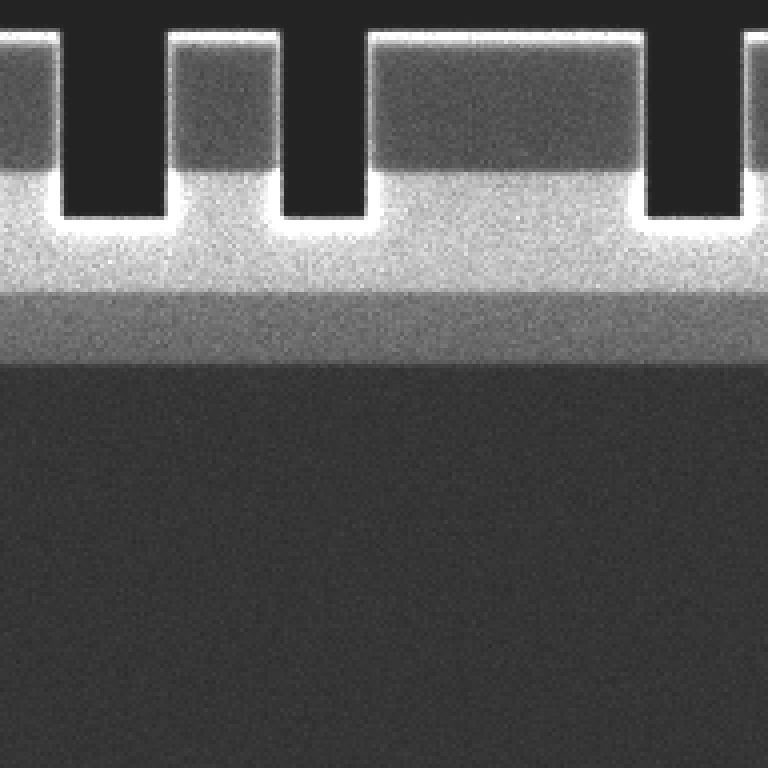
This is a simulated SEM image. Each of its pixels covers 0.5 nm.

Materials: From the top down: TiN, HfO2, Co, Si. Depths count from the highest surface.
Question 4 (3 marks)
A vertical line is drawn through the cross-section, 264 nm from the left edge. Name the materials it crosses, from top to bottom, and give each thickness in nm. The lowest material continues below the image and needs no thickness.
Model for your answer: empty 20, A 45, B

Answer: TiN 70, HfO2 60, Co 36, Si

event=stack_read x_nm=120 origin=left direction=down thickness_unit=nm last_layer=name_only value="TiN 70, HfO2 60, Co 36, Si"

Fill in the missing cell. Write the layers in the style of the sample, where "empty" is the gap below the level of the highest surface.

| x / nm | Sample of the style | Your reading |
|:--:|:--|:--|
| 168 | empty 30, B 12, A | empty 94, HfO2 36, Co 36, Si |